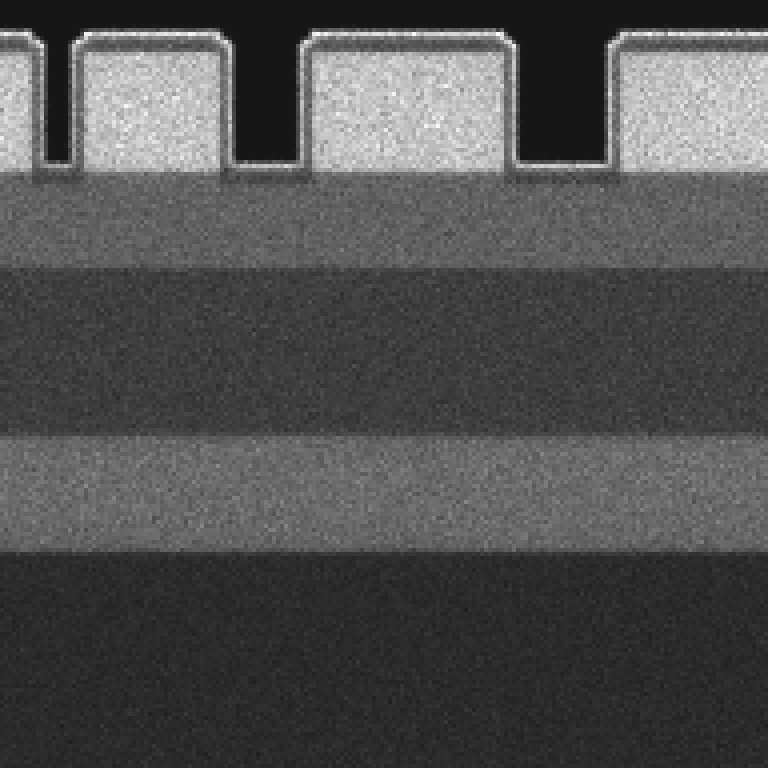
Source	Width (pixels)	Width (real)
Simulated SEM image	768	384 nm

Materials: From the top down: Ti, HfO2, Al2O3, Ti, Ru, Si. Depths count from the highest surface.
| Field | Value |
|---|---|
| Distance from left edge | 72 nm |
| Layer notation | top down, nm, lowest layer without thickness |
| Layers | Ti 10, HfO2 60, Al2O3 48, Ti 84, Ru 58, Si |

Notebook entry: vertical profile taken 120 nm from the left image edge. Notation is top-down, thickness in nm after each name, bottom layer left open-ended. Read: empty 66, Ti 10, Al2O3 42, Ti 84, Ru 58, Si